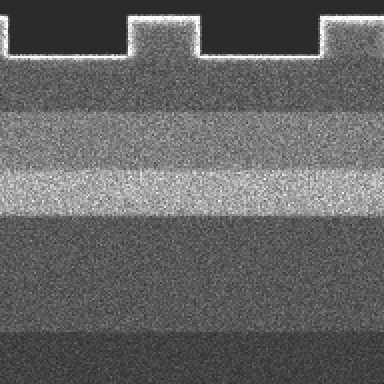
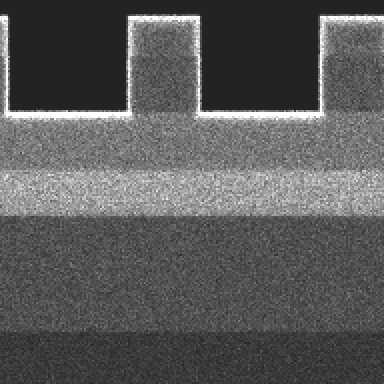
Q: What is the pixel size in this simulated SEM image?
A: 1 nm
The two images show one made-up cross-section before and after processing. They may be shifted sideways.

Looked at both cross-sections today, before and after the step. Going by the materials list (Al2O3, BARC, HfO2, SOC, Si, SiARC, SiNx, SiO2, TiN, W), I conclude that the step removed TiN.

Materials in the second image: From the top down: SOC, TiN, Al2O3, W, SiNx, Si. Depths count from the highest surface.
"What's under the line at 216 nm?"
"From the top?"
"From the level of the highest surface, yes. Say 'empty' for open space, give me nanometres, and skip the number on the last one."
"empty 96, Al2O3 58, W 46, SiNx 116, Si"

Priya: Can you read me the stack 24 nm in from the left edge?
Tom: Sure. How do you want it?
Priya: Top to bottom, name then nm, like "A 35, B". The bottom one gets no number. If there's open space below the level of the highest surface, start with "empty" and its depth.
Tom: empty 96, Al2O3 58, W 46, SiNx 116, Si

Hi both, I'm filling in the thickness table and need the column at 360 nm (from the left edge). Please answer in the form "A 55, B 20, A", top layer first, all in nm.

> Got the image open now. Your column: SOC 40, TiN 56, Al2O3 58, W 46, SiNx 116, Si